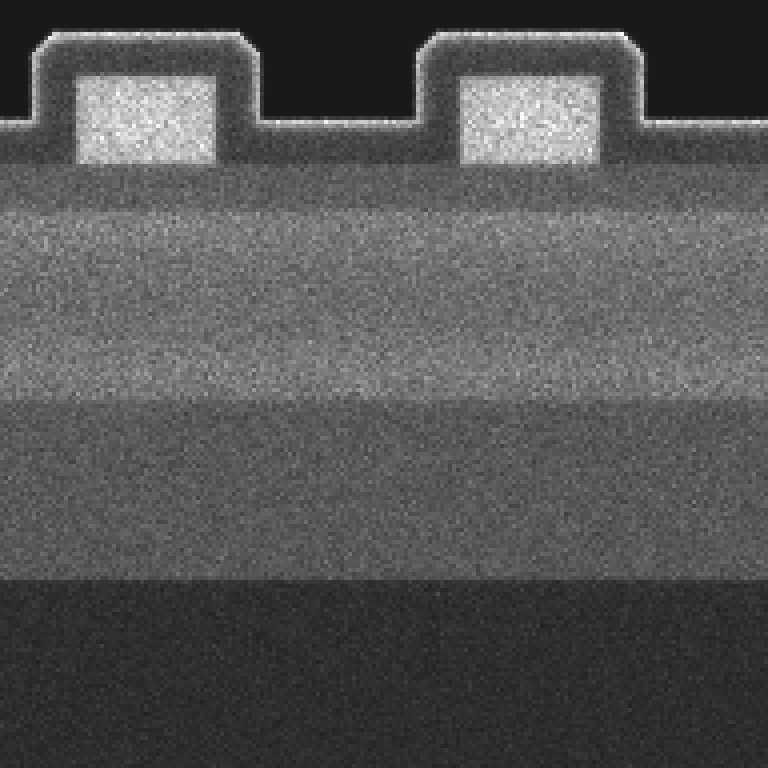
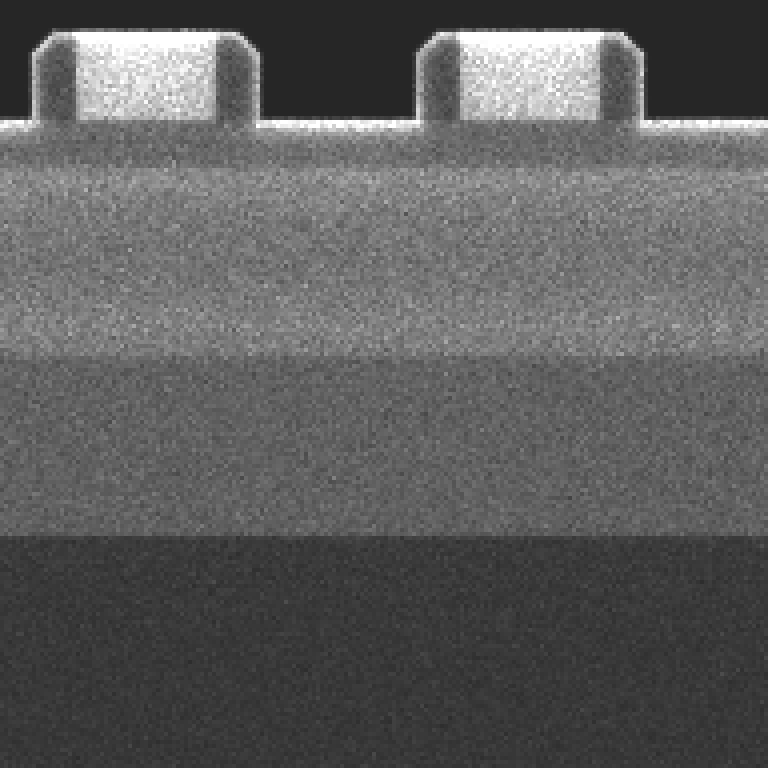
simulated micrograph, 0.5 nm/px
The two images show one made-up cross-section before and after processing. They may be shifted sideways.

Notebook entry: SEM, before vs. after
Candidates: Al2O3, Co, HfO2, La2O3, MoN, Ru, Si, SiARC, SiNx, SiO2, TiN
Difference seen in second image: SiNx removed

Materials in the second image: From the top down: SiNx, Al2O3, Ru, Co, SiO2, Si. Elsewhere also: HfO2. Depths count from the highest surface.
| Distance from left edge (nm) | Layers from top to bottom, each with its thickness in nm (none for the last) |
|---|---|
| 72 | HfO2 44, Al2O3 24, Ru 82, Co 12, SiO2 90, Si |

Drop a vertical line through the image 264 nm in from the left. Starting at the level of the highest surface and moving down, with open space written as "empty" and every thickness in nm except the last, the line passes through HfO2 44, Al2O3 24, Ru 82, Co 12, SiO2 90, Si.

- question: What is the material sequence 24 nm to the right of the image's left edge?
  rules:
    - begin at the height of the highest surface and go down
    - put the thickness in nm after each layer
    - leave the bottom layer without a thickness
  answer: empty 2, SiNx 42, Al2O3 24, Ru 82, Co 12, SiO2 90, Si